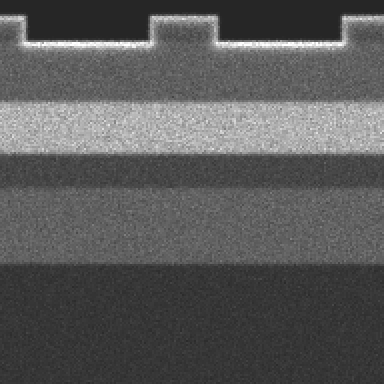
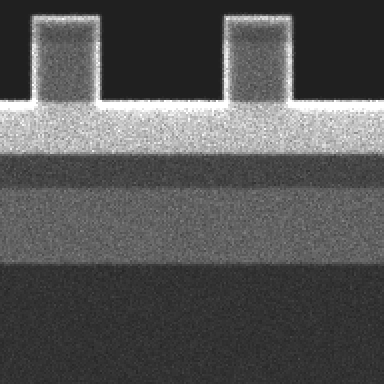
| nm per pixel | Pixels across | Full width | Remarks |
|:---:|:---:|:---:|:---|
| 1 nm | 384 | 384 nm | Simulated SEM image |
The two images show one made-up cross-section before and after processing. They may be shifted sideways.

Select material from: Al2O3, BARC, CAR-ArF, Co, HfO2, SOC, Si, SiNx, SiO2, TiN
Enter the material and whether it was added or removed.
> SiO2 / removed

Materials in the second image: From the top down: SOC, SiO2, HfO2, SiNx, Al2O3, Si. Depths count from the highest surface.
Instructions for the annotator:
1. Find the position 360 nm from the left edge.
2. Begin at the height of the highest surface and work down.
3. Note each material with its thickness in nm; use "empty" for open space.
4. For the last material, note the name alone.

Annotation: empty 86, HfO2 52, SiNx 34, Al2O3 76, Si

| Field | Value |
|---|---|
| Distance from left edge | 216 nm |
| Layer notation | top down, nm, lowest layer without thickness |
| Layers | empty 86, HfO2 52, SiNx 34, Al2O3 76, Si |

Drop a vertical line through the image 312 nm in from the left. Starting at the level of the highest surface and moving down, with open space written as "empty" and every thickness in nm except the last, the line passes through empty 86, HfO2 52, SiNx 34, Al2O3 76, Si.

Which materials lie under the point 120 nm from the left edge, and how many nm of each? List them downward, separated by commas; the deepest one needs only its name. empty 86, HfO2 52, SiNx 34, Al2O3 76, Si